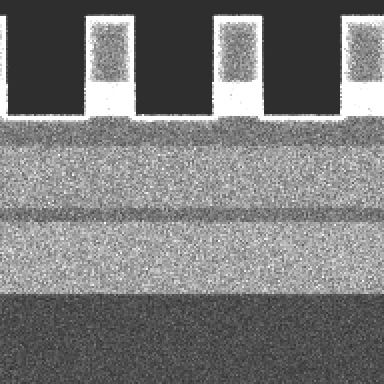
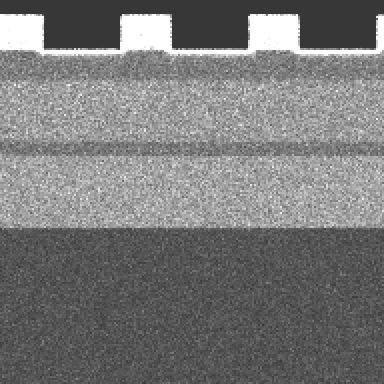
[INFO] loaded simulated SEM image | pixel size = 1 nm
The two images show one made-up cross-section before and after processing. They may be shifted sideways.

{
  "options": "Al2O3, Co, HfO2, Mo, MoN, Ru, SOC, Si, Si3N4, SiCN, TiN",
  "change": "removed",
  "material": "SOC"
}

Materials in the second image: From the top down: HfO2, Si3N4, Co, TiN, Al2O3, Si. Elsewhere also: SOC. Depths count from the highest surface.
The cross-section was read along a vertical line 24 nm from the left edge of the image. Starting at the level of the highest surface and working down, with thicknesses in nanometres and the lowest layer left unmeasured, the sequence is HfO2 34, Si3N4 30, Co 62, TiN 14, Al2O3 72, Si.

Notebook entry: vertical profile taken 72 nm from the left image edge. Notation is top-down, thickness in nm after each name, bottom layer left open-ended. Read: empty 34, Si3N4 30, Co 62, TiN 14, Al2O3 72, Si